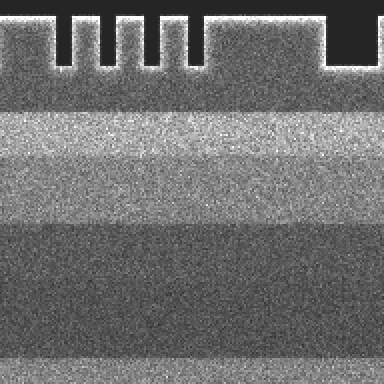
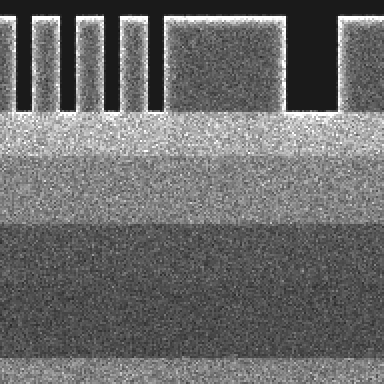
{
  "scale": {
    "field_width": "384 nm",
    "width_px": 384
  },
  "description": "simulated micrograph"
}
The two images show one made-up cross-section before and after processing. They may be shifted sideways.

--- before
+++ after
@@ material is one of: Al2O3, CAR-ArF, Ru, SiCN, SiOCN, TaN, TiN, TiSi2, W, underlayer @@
underlayer removed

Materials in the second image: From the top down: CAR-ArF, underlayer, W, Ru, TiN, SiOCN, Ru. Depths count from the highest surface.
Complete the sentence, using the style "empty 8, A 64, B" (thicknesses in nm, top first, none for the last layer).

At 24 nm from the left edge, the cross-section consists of empty 96, W 44, Ru 68, TiN 58, SiOCN 76, Ru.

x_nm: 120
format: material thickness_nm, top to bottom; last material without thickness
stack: CAR-ArF 50, underlayer 46, W 44, Ru 68, TiN 58, SiOCN 76, Ru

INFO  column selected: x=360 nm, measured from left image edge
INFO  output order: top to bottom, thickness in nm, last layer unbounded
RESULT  CAR-ArF 50, underlayer 46, W 44, Ru 68, TiN 58, SiOCN 76, Ru